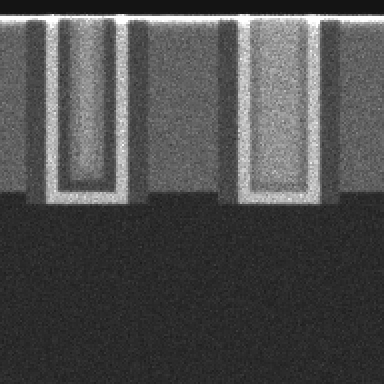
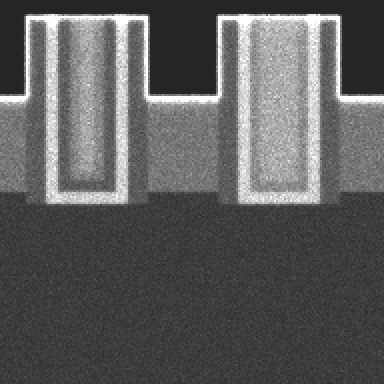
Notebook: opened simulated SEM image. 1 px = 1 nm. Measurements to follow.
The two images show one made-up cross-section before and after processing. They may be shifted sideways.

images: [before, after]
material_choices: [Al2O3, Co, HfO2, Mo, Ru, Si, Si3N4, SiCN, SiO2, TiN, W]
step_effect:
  removed: SiO2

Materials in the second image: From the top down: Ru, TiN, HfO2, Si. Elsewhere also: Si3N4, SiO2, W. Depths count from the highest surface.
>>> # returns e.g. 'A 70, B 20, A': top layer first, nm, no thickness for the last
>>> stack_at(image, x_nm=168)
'empty 80, SiO2 96, Si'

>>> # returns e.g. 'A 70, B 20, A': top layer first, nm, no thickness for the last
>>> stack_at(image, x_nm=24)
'empty 80, SiO2 96, Si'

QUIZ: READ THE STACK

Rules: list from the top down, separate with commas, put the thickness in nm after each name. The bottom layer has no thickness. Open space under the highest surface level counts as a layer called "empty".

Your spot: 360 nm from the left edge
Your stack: empty 80, SiO2 96, Si